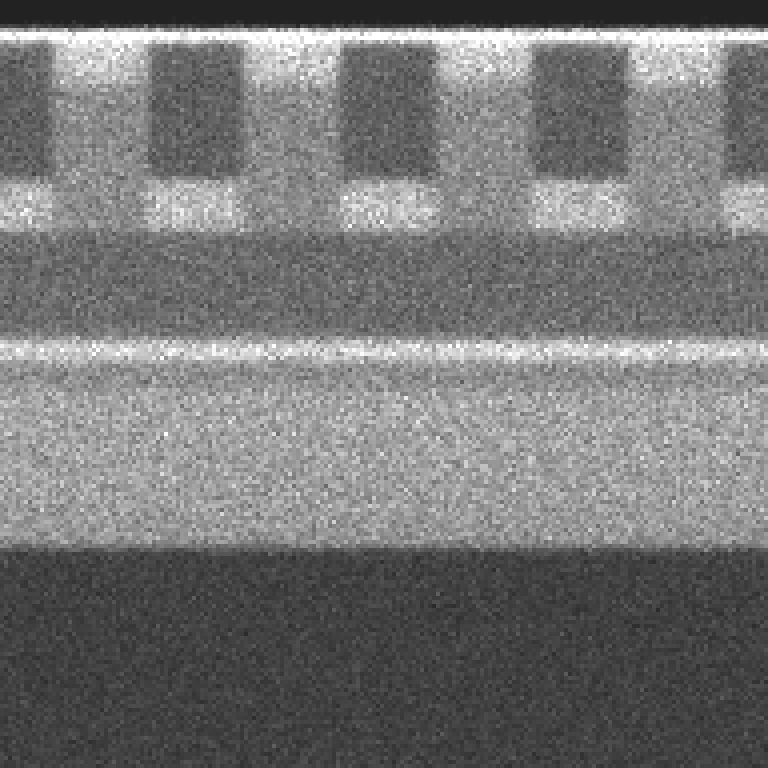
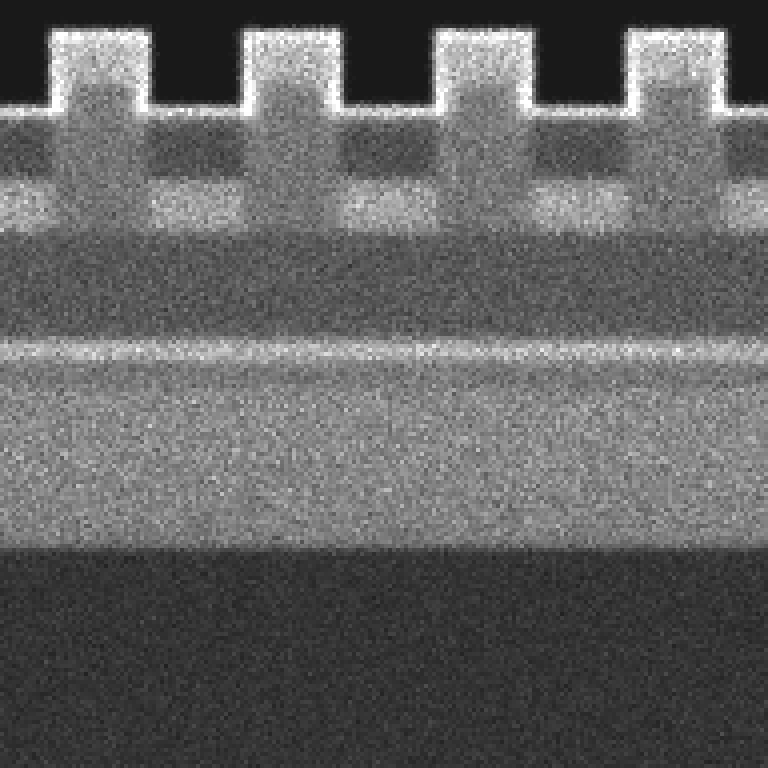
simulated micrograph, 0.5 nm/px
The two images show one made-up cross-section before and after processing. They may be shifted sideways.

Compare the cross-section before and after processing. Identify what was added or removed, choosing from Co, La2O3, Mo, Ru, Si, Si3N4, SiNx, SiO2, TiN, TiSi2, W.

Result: SiNx removed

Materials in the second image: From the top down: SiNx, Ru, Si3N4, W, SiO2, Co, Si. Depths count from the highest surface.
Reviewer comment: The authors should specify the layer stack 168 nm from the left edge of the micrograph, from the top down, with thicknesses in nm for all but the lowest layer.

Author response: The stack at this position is Ru 26, SiO2 74, Si3N4 54, W 10, SiO2 14, Co 80, Si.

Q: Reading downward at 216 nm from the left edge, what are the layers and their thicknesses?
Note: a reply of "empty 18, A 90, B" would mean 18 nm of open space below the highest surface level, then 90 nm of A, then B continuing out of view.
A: empty 38, SiNx 36, Ru 26, Si3N4 54, W 10, SiO2 14, Co 80, Si